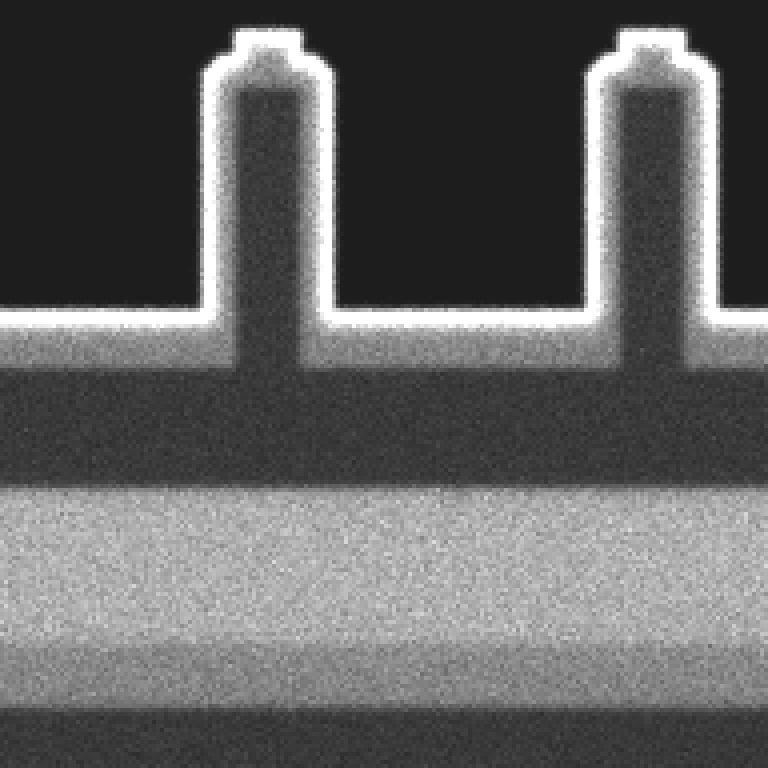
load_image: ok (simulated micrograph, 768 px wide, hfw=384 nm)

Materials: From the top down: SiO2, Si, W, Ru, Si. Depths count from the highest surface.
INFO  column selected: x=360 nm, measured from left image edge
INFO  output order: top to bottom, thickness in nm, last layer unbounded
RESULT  empty 140, SiO2 28, Si 60, W 78, Ru 32, Si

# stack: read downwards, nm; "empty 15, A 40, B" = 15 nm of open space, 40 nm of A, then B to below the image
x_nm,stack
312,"SiO2 28, Si 200, W 78, Ru 32, Si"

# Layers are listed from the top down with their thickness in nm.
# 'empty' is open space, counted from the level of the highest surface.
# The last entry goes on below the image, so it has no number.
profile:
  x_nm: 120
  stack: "SiO2 28, Si 200, W 78, Ru 32, Si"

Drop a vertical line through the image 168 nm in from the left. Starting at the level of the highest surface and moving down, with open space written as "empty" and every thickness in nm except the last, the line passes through empty 140, SiO2 28, Si 60, W 78, Ru 32, Si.